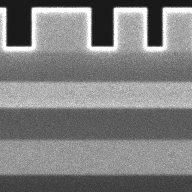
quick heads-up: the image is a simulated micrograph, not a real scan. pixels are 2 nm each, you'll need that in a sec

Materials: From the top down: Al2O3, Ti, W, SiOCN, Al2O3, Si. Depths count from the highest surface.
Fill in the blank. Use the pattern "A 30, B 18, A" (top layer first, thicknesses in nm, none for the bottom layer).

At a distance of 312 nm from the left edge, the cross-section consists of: empty 78, Al2O3 10, Ti 60, W 52, SiOCN 64, Al2O3 70, Si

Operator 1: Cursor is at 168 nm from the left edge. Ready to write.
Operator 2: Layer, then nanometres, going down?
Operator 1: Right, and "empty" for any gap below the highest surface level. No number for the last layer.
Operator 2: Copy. Al2O3 88, Ti 60, W 52, SiOCN 64, Al2O3 70, Si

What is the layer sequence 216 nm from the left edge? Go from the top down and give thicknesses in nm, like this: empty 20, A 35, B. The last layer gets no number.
empty 78, Al2O3 10, Ti 60, W 52, SiOCN 64, Al2O3 70, Si